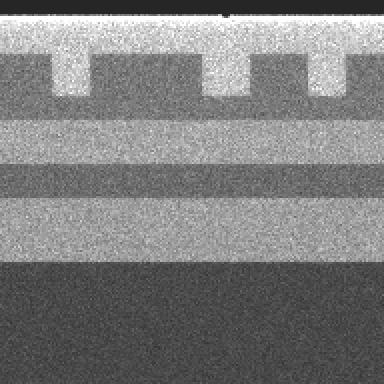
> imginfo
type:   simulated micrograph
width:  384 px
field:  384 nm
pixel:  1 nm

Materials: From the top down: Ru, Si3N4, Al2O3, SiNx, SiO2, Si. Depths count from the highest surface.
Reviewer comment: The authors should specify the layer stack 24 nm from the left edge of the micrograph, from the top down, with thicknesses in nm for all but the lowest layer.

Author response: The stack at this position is Ru 38, Si3N4 66, Al2O3 44, SiNx 34, SiO2 64, Si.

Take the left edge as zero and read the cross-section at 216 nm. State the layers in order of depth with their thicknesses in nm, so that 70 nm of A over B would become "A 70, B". Ru 80, Si3N4 24, Al2O3 44, SiNx 34, SiO2 64, Si